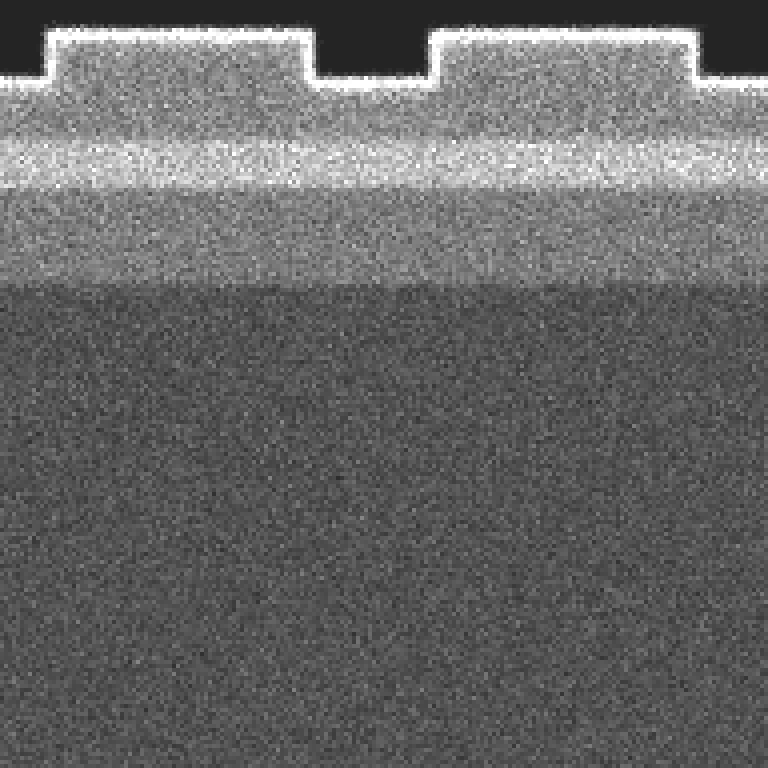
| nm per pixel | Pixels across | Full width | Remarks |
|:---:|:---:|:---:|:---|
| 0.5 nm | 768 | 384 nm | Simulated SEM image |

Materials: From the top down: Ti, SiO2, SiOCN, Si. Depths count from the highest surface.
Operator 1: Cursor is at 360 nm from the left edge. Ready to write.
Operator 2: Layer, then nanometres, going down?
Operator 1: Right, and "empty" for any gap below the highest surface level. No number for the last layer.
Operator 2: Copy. empty 24, Ti 30, SiO2 24, SiOCN 48, Si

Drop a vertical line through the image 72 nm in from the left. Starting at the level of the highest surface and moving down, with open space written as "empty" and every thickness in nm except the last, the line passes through Ti 54, SiO2 24, SiOCN 48, Si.